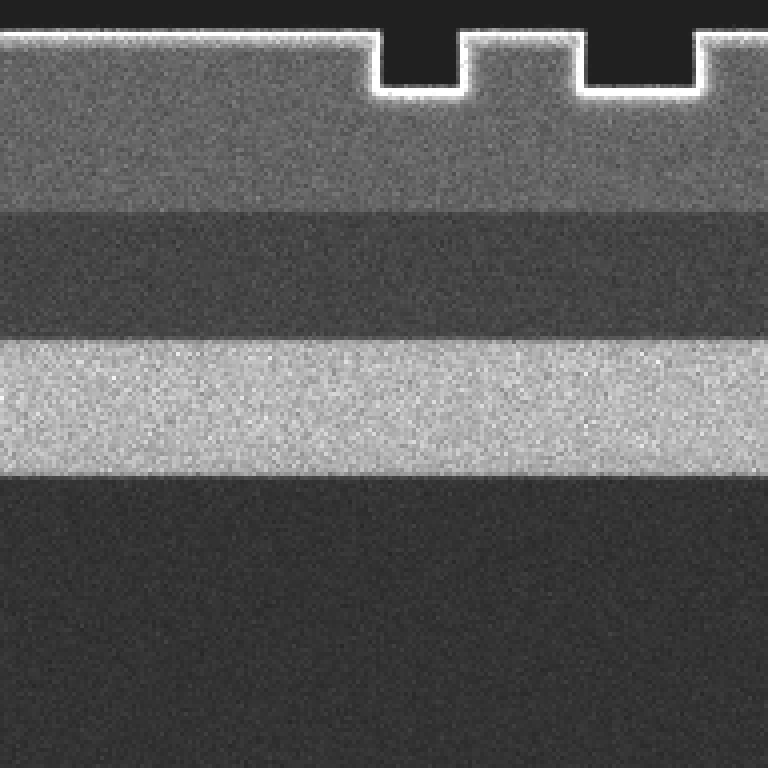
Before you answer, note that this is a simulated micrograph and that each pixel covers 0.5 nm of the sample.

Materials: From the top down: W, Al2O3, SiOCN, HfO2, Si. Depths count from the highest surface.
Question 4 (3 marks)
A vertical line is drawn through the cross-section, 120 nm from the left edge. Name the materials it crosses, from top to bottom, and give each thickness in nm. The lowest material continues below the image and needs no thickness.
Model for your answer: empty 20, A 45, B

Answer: W 8, Al2O3 82, SiOCN 64, HfO2 68, Si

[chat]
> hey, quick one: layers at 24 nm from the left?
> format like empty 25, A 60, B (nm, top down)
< W 8, Al2O3 82, SiOCN 64, HfO2 68, Si